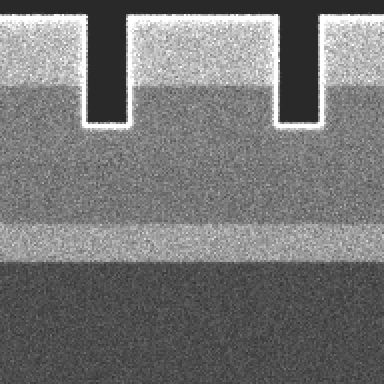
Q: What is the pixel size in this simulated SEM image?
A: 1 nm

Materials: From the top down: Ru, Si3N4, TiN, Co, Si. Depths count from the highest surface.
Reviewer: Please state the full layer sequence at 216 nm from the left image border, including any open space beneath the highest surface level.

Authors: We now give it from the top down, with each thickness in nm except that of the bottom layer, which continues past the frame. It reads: Ru 70, Si3N4 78, TiN 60, Co 38, Si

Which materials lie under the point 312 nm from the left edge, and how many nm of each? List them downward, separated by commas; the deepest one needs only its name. empty 108, Si3N4 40, TiN 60, Co 38, Si